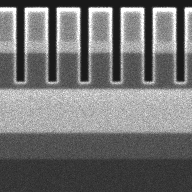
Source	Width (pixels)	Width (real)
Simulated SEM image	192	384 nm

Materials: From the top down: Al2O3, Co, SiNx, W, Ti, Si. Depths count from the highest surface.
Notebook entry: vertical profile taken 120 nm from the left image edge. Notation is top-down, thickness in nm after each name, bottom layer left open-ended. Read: Al2O3 66, Co 24, SiNx 72, W 88, Ti 52, Si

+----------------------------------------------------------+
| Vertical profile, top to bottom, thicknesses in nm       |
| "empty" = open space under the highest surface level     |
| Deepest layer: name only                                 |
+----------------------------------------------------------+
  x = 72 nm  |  Al2O3 66, Co 24, SiNx 72, W 88, Ti 52, Si